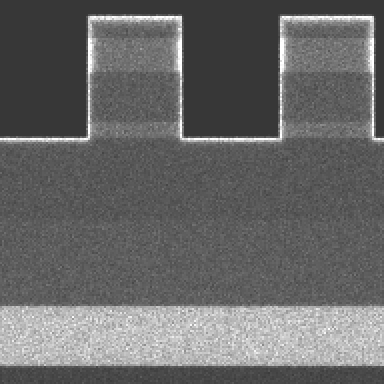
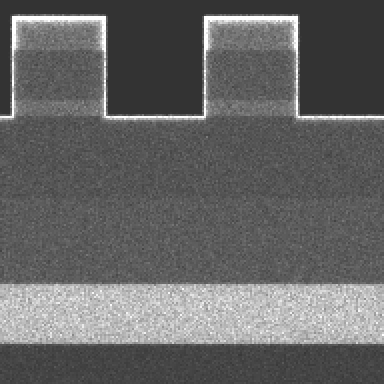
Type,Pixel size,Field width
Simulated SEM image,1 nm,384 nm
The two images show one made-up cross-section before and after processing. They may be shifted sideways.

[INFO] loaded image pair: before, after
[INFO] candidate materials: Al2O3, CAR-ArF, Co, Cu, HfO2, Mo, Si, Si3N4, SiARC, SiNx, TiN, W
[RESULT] removed SiARC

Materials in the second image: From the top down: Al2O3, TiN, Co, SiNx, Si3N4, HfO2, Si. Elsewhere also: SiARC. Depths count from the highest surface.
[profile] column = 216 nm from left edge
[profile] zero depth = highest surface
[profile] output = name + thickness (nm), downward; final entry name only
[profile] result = Al2O3 34, TiN 50, Co 16, SiNx 82, Si3N4 86, HfO2 60, Si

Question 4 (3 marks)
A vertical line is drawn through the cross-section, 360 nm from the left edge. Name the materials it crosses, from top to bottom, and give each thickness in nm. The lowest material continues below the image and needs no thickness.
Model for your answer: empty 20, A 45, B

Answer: empty 100, SiNx 82, Si3N4 86, HfO2 60, Si